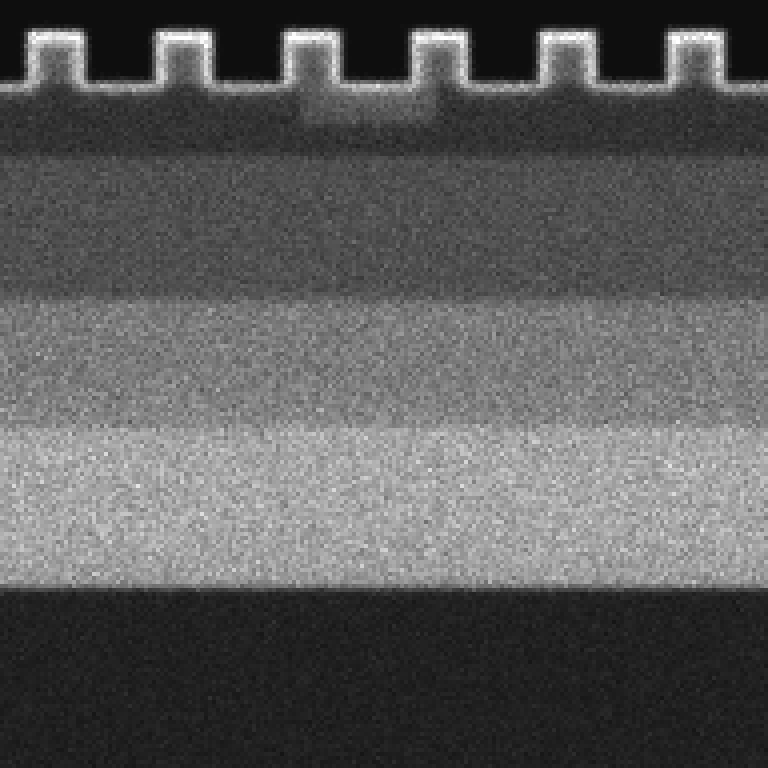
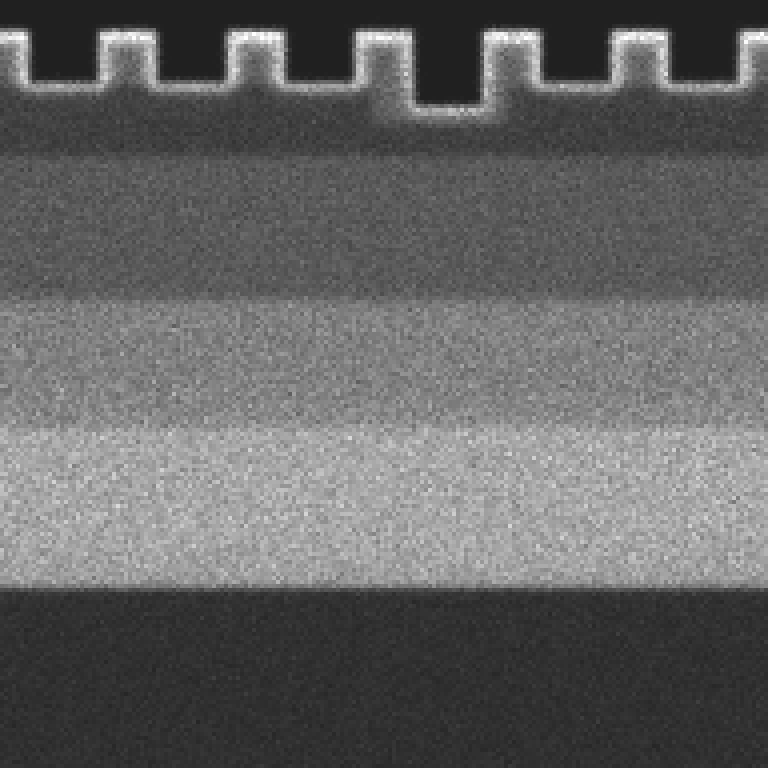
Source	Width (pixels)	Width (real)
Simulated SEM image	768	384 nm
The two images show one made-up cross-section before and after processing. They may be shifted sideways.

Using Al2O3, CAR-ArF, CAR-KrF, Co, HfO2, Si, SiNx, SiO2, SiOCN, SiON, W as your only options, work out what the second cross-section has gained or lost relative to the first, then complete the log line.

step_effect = removed Co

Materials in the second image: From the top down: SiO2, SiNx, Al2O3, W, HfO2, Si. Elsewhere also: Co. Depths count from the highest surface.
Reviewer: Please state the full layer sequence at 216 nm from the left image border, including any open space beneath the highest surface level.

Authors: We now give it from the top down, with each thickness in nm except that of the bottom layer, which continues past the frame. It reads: empty 38, Co 8, SiNx 16, Al2O3 72, W 64, HfO2 80, Si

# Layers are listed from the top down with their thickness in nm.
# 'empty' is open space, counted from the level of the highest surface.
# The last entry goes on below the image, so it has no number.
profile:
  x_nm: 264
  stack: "SiO2 26, SiNx 36, Al2O3 72, W 64, HfO2 80, Si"